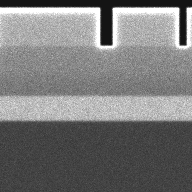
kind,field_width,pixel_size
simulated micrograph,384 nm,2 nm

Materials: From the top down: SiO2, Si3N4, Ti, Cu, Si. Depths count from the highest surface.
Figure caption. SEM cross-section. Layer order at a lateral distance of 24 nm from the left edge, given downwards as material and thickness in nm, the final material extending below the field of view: SiO2 76, Si3N4 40, Ti 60, Cu 50, Si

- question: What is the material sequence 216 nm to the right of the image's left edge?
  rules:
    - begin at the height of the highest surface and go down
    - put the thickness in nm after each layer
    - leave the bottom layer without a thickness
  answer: empty 76, Si3N4 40, Ti 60, Cu 50, Si